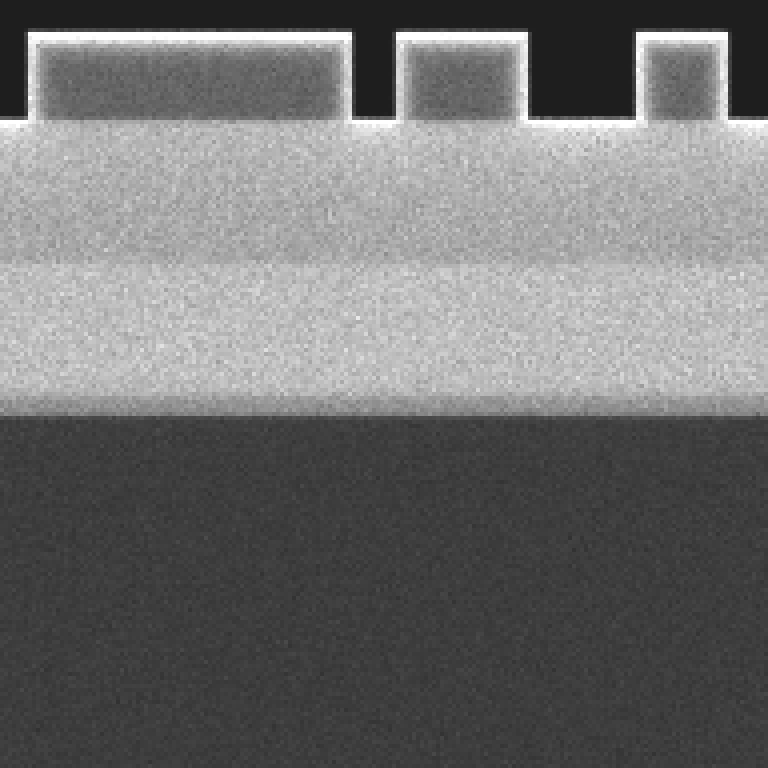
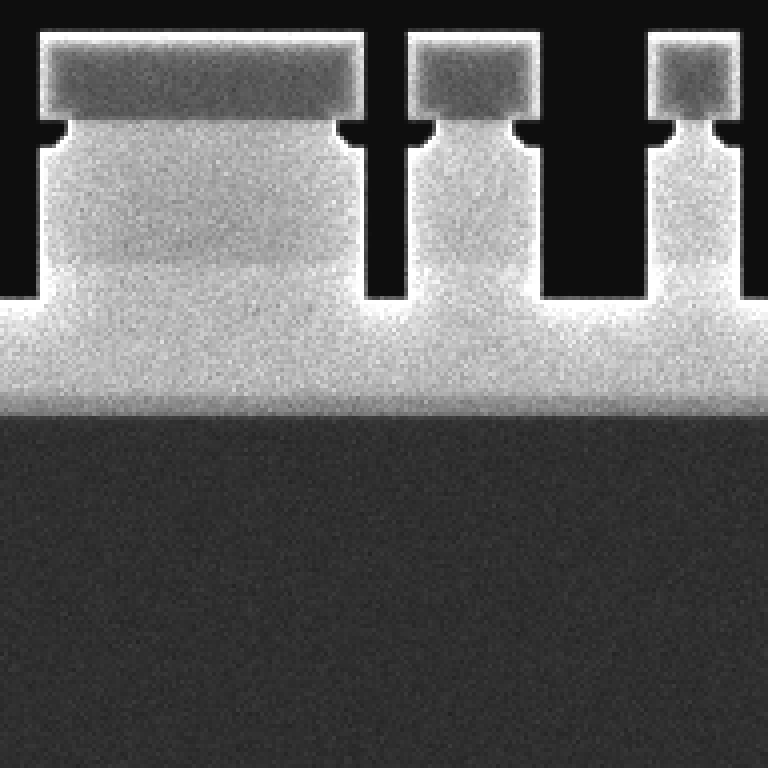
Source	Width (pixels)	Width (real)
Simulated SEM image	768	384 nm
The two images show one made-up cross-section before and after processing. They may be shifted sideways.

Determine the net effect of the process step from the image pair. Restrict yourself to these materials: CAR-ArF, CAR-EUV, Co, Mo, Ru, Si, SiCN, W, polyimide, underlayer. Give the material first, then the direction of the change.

Ru and W: removed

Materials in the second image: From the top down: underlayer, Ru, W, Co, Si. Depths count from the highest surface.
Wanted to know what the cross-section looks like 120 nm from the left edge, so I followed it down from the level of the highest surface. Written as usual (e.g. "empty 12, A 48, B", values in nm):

underlayer 44, Ru 72, W 66, Co 10, Si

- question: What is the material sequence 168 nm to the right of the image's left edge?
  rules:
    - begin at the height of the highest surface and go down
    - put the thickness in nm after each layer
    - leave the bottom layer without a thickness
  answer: underlayer 44, empty 8, Ru 64, W 66, Co 10, Si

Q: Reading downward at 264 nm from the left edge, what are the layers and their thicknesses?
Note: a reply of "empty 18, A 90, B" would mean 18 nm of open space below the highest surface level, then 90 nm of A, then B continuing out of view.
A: underlayer 44, empty 14, Ru 58, W 66, Co 10, Si